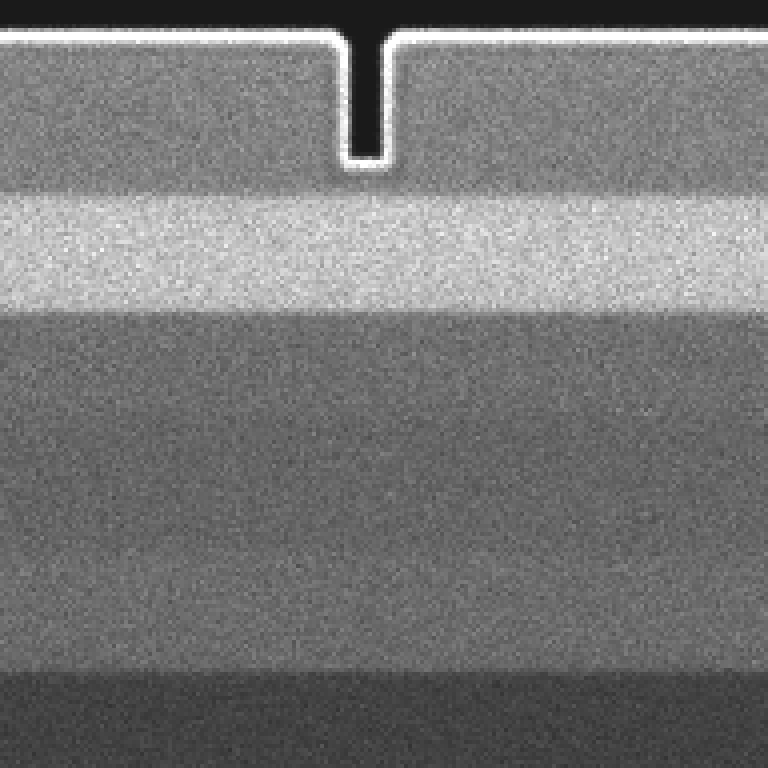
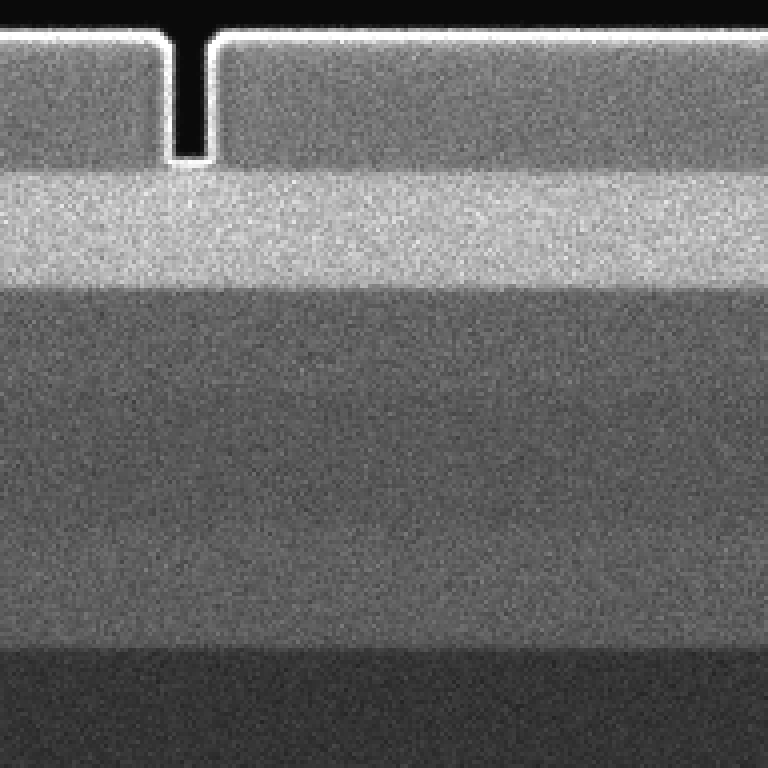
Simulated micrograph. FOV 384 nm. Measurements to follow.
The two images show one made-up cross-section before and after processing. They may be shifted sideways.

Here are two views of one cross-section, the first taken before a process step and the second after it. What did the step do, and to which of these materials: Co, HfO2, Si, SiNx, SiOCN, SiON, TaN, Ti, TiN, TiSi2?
It removed SiNx.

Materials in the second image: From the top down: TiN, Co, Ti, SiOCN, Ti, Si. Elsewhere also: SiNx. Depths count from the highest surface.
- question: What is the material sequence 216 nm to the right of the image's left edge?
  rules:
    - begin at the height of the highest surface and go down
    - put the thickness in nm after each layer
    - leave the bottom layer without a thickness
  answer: TiN 70, Co 58, Ti 52, SiOCN 68, Ti 60, Si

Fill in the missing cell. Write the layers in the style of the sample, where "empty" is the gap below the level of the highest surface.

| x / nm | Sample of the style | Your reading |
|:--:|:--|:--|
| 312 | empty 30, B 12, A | TiN 70, Co 58, Ti 52, SiOCN 68, Ti 60, Si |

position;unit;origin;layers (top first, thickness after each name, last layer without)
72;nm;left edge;TiN 70, Co 58, Ti 52, SiOCN 68, Ti 60, Si